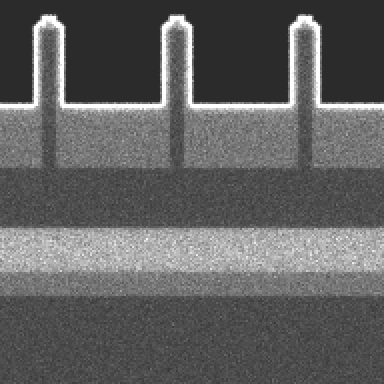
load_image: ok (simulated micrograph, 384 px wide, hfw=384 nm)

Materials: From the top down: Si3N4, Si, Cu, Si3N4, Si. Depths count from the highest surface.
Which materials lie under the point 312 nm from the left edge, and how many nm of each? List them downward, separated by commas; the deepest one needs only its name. empty 6, Si3N4 146, Si 60, Cu 44, Si3N4 24, Si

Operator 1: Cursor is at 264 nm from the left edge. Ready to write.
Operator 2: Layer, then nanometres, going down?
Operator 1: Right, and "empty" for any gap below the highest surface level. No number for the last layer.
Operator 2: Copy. empty 88, Si3N4 64, Si 60, Cu 44, Si3N4 24, Si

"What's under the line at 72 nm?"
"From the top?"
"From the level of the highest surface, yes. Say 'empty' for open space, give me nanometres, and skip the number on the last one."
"empty 88, Si3N4 64, Si 60, Cu 44, Si3N4 24, Si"